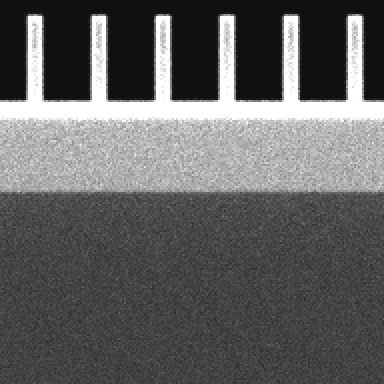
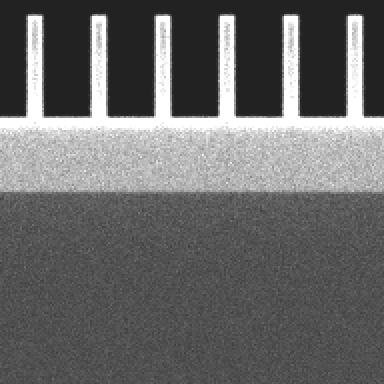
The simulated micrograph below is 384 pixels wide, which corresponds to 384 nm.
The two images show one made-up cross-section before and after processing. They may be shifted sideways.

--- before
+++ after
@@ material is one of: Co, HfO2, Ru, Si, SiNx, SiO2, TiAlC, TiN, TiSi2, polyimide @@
Ru removed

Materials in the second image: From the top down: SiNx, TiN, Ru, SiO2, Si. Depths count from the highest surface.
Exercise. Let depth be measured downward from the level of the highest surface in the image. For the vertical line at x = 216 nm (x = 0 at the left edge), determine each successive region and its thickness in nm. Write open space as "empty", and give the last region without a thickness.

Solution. empty 102, SiO2 74, Si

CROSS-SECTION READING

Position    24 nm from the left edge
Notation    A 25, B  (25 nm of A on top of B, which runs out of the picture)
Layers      empty 102, SiO2 74, Si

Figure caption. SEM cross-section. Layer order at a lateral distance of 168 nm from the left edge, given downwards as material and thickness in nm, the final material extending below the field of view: SiNx 32, TiN 54, Ru 16, SiO2 74, Si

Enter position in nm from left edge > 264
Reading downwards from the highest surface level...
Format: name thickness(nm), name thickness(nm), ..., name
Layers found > empty 102, SiO2 74, Si